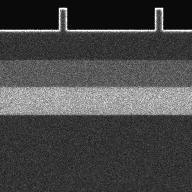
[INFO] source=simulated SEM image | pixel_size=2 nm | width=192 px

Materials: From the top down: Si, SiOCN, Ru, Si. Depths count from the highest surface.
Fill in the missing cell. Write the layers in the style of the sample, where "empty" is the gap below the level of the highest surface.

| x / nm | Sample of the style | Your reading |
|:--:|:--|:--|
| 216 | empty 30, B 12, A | empty 44, Si 60, SiOCN 54, Ru 56, Si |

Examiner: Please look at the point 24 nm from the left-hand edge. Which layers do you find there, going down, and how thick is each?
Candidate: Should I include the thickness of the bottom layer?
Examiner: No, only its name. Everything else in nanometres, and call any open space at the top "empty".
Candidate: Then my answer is empty 44, Si 60, SiOCN 54, Ru 56, Si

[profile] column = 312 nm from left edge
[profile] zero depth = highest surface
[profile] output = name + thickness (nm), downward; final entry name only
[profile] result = Si 104, SiOCN 54, Ru 56, Si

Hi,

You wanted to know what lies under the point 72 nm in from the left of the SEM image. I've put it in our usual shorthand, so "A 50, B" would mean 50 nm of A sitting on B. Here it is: empty 44, Si 60, SiOCN 54, Ru 56, Si